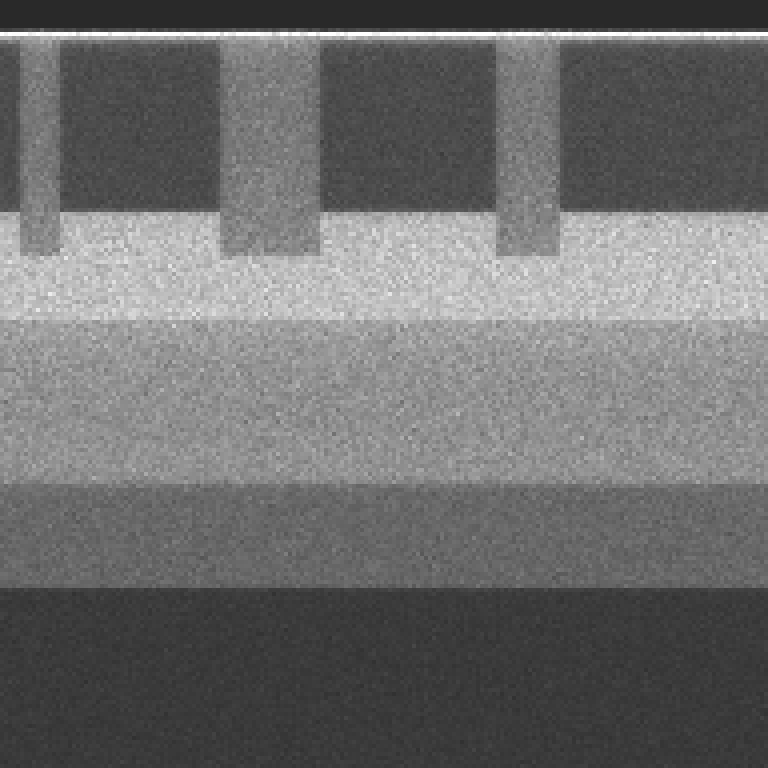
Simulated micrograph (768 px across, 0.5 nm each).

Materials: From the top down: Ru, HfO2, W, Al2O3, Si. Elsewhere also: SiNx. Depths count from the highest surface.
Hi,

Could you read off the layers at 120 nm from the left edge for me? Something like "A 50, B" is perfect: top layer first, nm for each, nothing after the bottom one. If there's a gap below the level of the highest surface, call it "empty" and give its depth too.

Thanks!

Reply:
Ru 112, HfO2 32, W 82, Al2O3 52, Si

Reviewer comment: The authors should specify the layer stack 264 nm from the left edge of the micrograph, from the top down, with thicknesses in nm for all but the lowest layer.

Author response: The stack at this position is Ru 112, HfO2 32, W 82, Al2O3 52, Si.